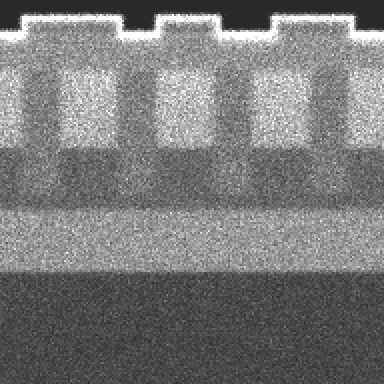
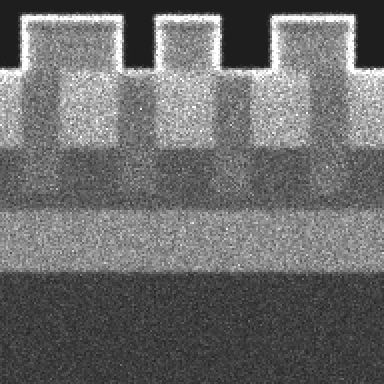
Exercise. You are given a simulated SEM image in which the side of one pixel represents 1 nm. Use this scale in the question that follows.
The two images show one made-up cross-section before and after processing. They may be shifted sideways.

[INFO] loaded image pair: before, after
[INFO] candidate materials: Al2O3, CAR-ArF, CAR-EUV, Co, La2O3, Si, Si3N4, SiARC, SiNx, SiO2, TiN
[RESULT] removed SiO2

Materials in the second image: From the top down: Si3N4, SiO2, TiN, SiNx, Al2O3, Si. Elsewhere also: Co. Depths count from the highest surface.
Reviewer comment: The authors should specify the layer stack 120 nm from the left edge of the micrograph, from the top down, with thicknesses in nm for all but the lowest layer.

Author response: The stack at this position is Si3N4 16, SiO2 38, TiN 124, SiNx 16, Al2O3 62, Si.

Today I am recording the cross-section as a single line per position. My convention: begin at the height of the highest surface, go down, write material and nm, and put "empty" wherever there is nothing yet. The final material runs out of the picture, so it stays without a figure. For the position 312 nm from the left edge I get Si3N4 16, SiO2 38, TiN 124, SiNx 16, Al2O3 62, Si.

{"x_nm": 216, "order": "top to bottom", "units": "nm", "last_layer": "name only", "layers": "Si3N4 16, SiO2 38, TiN 124, SiNx 16, Al2O3 62, Si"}